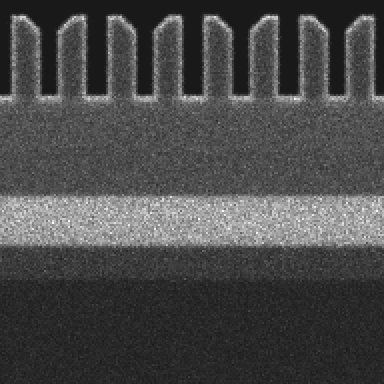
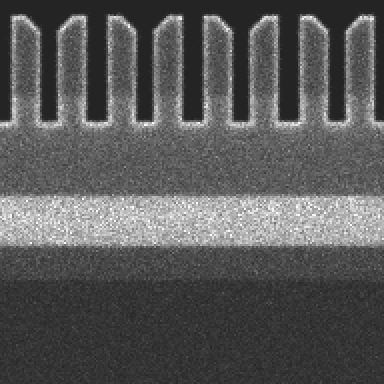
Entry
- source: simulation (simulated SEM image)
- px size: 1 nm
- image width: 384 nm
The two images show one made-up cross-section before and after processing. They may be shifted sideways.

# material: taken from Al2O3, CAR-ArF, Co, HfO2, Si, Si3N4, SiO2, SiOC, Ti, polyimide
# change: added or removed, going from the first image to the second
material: Al2O3
change: removed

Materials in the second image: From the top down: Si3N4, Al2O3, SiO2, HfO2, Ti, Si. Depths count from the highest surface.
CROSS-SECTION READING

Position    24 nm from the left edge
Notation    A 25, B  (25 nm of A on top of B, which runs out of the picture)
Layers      Si3N4 80, Al2O3 54, SiO2 46, HfO2 50, Ti 34, Si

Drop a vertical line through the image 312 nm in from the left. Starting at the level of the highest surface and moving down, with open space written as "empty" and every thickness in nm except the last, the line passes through Si3N4 80, Al2O3 54, SiO2 46, HfO2 50, Ti 34, Si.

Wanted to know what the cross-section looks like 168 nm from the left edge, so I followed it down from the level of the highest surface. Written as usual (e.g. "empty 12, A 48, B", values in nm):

Si3N4 80, Al2O3 54, SiO2 46, HfO2 50, Ti 34, Si